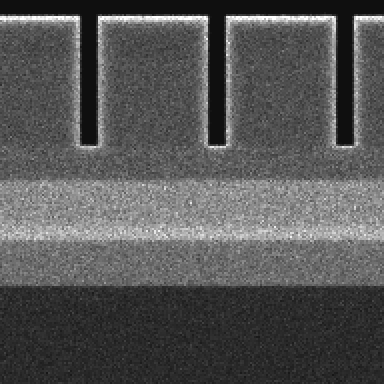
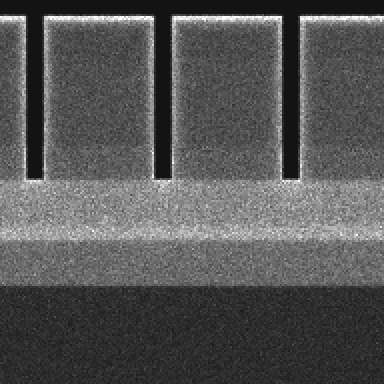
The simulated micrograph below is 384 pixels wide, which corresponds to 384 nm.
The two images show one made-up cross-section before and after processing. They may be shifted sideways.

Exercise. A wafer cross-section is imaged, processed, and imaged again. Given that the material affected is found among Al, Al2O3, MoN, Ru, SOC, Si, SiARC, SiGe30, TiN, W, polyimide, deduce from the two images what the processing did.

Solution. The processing removed TiN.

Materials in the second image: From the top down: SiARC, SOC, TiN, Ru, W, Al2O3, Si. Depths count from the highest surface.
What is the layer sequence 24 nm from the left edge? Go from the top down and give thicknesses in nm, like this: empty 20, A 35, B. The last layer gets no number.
SiARC 42, SOC 88, TiN 34, Ru 46, W 14, Al2O3 46, Si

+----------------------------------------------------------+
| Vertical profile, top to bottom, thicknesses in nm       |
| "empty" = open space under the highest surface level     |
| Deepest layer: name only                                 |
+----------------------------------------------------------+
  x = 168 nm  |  empty 164, Ru 46, W 14, Al2O3 46, Si